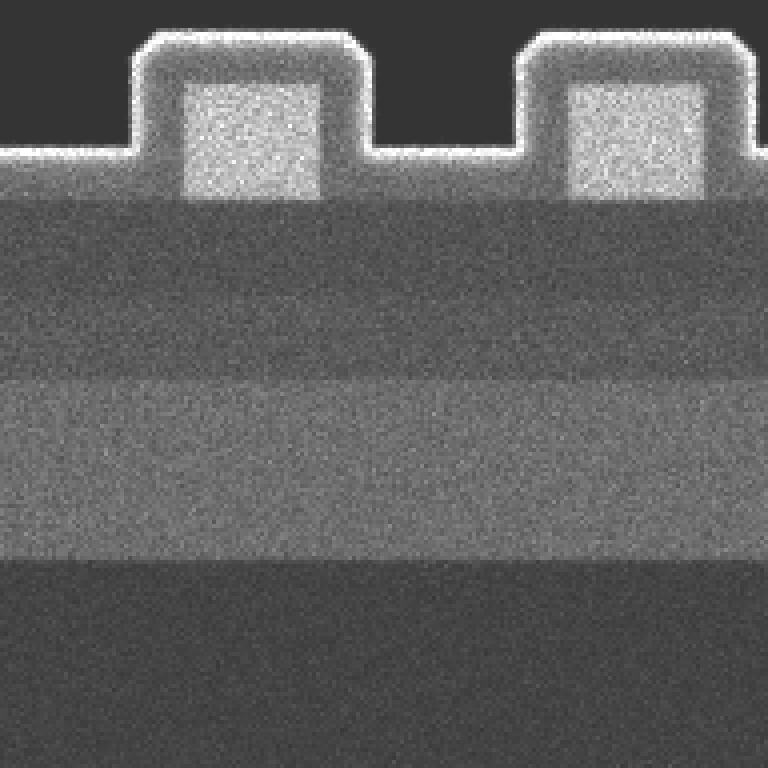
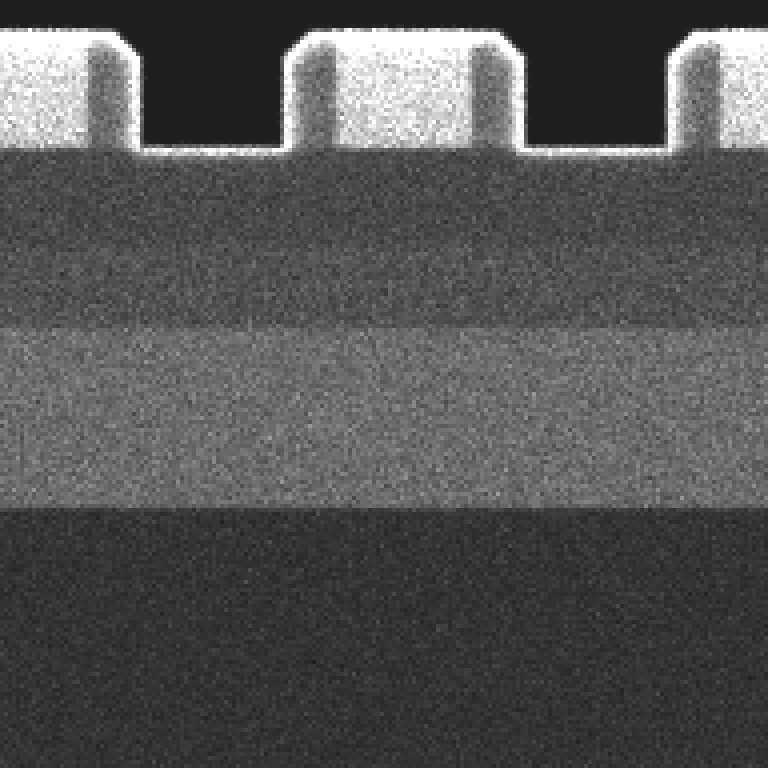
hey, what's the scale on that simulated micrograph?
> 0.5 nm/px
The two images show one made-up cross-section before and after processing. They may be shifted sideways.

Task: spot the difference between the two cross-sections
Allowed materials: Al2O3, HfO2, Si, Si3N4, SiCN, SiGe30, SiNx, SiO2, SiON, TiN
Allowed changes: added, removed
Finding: removed SiO2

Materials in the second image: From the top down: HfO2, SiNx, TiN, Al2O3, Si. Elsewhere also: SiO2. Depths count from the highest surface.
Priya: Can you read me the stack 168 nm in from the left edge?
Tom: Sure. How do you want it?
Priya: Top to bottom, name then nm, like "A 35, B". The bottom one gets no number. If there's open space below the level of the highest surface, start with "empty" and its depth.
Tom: HfO2 58, SiNx 48, TiN 42, Al2O3 90, Si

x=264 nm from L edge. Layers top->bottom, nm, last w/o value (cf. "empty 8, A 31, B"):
empty 58, SiNx 48, TiN 42, Al2O3 90, Si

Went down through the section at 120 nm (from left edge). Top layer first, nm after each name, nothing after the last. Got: empty 58, SiNx 48, TiN 42, Al2O3 90, Si